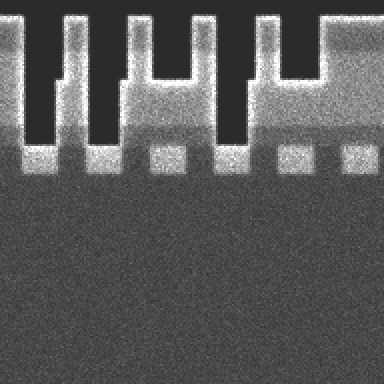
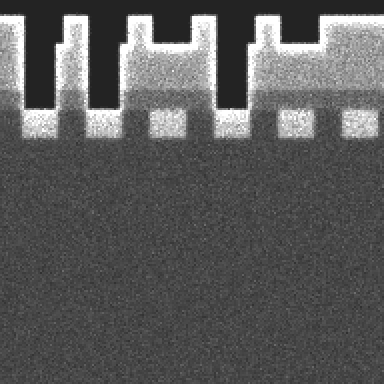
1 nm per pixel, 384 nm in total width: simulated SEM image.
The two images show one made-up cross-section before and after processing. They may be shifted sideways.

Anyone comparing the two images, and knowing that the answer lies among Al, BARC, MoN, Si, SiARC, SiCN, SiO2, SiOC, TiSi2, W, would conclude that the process removed SiARC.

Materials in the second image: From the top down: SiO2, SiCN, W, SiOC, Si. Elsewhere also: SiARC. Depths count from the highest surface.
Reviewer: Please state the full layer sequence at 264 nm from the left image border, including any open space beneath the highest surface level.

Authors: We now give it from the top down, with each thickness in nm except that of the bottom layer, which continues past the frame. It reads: SiO2 74, SiCN 20, SiOC 66, Si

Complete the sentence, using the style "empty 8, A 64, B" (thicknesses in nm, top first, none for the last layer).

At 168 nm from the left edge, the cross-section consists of empty 28, SiO2 46, SiCN 20, W 28, SiOC 38, Si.